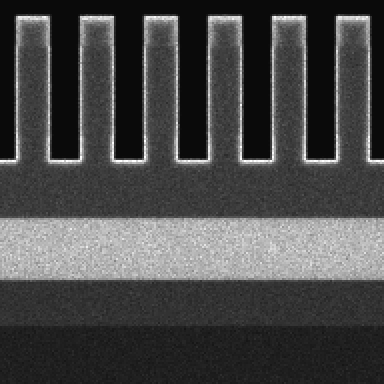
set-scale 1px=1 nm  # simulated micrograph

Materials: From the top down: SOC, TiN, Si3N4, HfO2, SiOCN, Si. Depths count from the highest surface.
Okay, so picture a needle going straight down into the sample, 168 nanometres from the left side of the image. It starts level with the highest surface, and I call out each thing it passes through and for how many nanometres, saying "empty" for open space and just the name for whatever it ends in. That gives SOC 30, TiN 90, Si3N4 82, HfO2 62, SiOCN 46, Si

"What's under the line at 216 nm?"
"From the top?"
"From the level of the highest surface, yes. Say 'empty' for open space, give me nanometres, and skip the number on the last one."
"SOC 30, TiN 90, Si3N4 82, HfO2 62, SiOCN 46, Si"